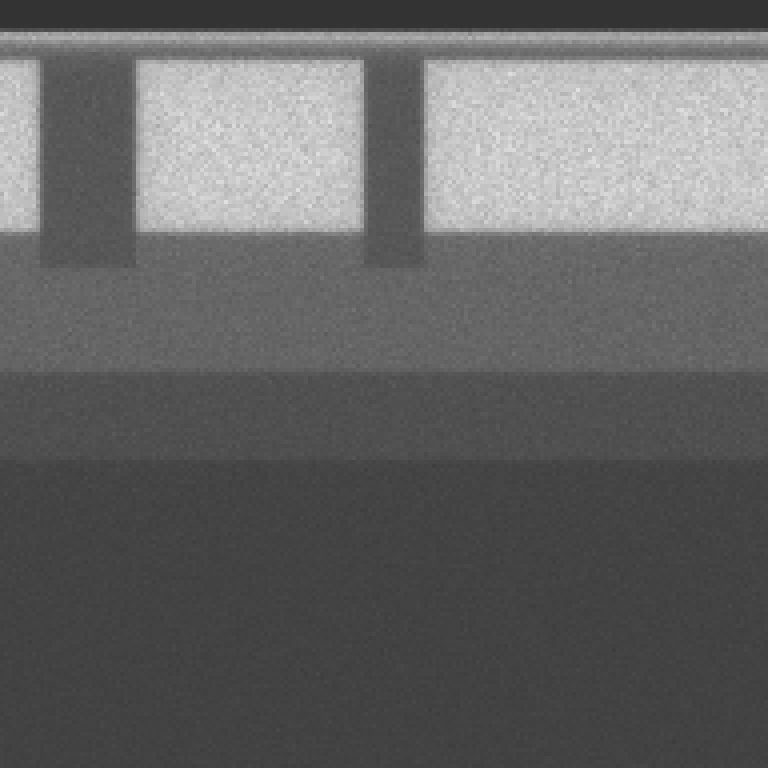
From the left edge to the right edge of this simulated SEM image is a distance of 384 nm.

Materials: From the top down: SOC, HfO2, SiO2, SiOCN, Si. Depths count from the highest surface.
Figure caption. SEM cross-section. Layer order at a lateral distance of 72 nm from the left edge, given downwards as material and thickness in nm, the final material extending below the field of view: SOC 14, HfO2 86, SiO2 70, SiOCN 44, Si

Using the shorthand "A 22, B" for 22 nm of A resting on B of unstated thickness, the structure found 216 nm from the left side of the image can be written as SOC 14, HfO2 86, SiO2 70, SiOCN 44, Si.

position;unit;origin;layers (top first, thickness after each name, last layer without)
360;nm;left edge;SOC 14, HfO2 86, SiO2 70, SiOCN 44, Si